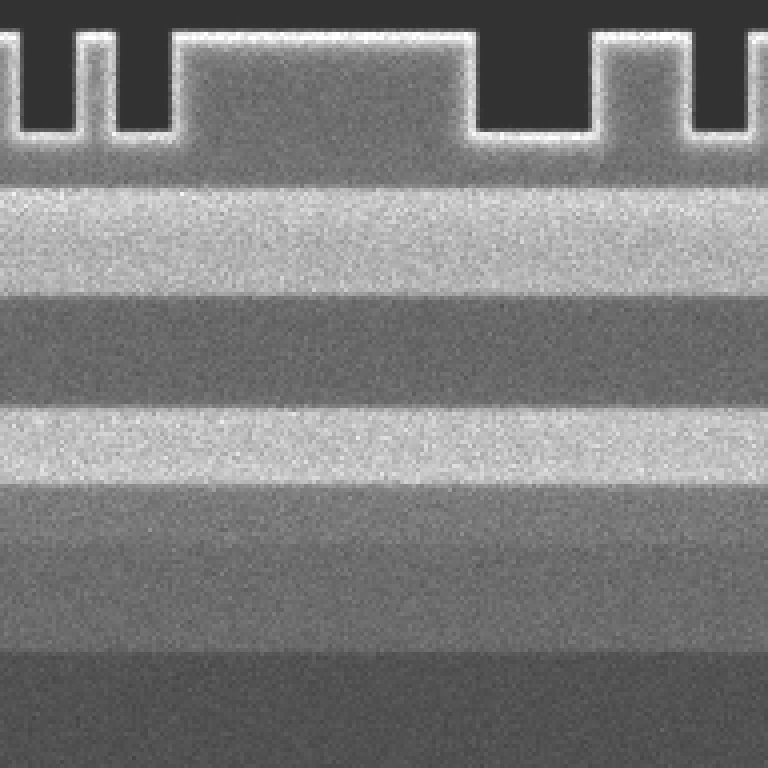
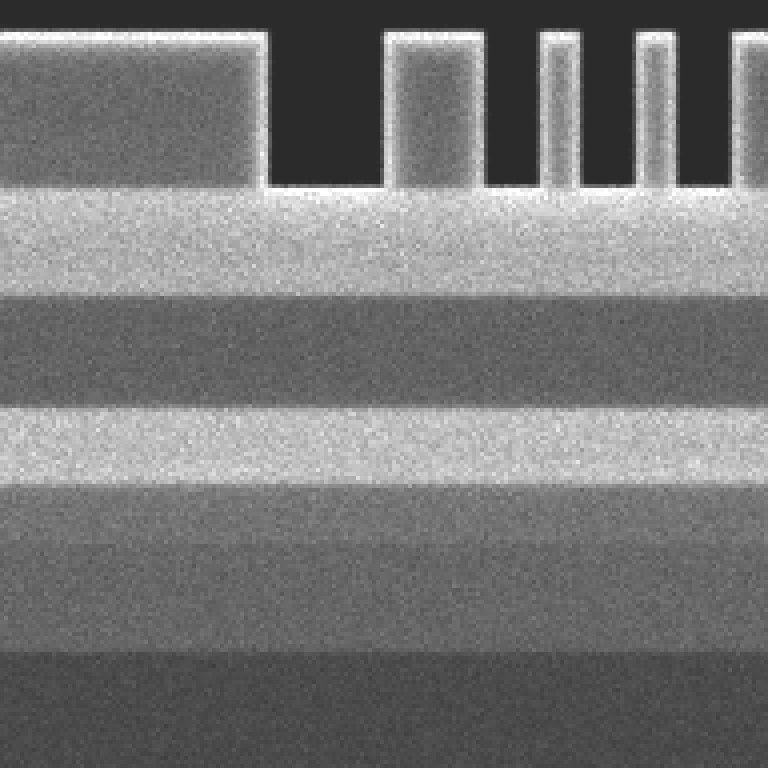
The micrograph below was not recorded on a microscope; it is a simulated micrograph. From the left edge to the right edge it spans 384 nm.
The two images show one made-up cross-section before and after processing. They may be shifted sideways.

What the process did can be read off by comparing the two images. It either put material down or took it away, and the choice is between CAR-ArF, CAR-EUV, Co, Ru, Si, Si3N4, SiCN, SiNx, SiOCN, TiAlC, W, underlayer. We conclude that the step removed underlayer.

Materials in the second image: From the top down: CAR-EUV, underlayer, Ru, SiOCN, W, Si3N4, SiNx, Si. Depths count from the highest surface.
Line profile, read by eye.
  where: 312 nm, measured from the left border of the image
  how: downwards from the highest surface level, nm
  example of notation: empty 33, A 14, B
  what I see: empty 78, Ru 54, SiOCN 56, W 38, Si3N4 30, SiNx 54, Si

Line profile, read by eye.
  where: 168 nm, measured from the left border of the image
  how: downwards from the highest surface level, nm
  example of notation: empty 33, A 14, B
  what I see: empty 78, Ru 54, SiOCN 56, W 38, Si3N4 30, SiNx 54, Si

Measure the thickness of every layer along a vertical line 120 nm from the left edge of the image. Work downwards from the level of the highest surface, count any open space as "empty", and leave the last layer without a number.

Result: CAR-EUV 50, underlayer 28, Ru 54, SiOCN 56, W 38, Si3N4 30, SiNx 54, Si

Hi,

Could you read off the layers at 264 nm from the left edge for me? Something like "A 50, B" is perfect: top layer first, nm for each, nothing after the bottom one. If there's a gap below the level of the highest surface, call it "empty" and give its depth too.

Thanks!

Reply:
empty 78, Ru 54, SiOCN 56, W 38, Si3N4 30, SiNx 54, Si